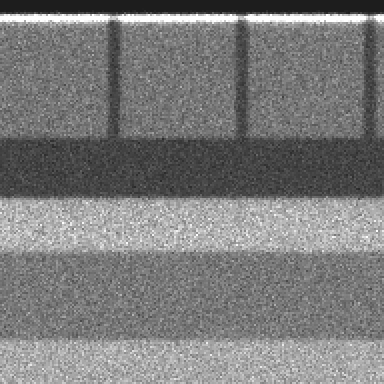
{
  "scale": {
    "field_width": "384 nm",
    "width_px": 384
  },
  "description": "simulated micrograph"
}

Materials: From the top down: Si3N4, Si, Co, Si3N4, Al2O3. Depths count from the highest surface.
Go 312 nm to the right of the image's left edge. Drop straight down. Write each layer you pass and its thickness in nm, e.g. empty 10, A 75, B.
Si3N4 122, Si 60, Co 54, Si3N4 88, Al2O3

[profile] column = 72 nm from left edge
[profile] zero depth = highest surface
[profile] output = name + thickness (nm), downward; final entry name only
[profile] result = Si3N4 122, Si 60, Co 54, Si3N4 88, Al2O3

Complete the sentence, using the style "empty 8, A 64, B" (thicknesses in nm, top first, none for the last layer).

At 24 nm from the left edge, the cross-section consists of Si3N4 122, Si 60, Co 54, Si3N4 88, Al2O3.